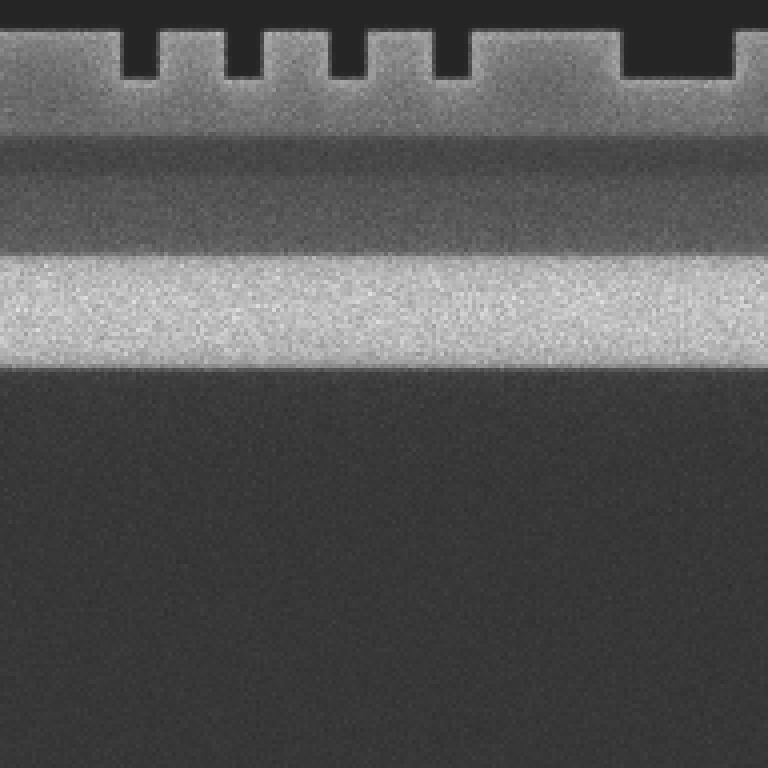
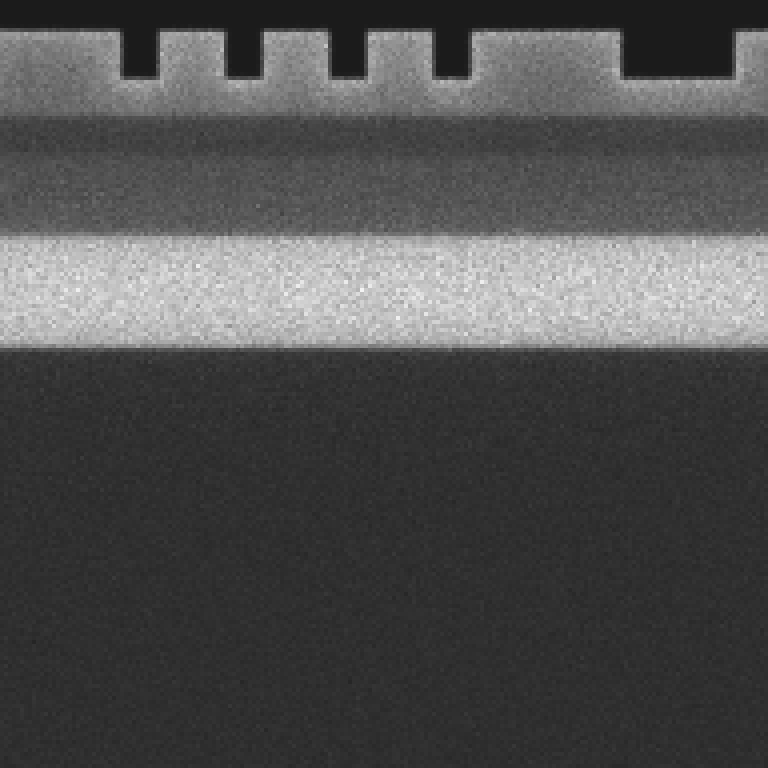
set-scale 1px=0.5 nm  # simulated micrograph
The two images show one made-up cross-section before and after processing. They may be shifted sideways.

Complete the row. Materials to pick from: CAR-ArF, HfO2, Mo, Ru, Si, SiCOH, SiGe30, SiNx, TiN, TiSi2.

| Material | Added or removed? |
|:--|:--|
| Ru | removed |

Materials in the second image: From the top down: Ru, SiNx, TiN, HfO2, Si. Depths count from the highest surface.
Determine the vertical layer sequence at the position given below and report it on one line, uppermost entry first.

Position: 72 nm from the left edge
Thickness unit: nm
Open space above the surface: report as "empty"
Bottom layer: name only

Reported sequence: empty 24, Ru 18, SiNx 20, TiN 40, HfO2 56, Si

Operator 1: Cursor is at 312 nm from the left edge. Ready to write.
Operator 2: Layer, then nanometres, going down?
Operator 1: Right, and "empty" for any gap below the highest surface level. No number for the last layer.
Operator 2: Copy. empty 24, Ru 18, SiNx 20, TiN 40, HfO2 56, Si